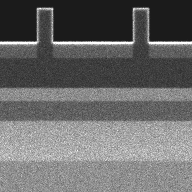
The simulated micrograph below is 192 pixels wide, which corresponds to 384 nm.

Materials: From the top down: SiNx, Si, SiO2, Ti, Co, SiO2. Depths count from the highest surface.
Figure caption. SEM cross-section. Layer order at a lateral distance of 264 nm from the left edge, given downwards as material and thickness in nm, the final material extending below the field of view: empty 68, SiNx 32, Si 60, SiO2 26, Ti 40, Co 80, SiO2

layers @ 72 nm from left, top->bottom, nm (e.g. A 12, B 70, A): empty 68, SiNx 32, Si 60, SiO2 26, Ti 40, Co 80, SiO2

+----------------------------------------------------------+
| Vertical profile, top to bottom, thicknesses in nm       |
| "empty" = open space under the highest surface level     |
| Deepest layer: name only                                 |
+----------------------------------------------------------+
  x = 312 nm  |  empty 68, SiNx 32, Si 60, SiO2 26, Ti 40, Co 80, SiO2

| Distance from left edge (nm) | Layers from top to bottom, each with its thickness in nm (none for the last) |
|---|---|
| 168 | empty 68, SiNx 32, Si 60, SiO2 26, Ti 40, Co 80, SiO2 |